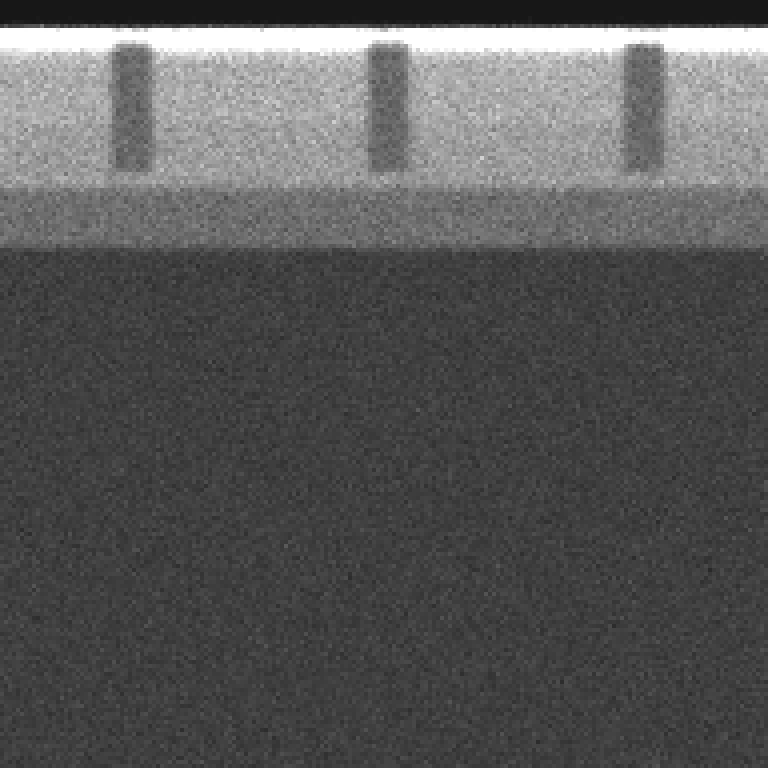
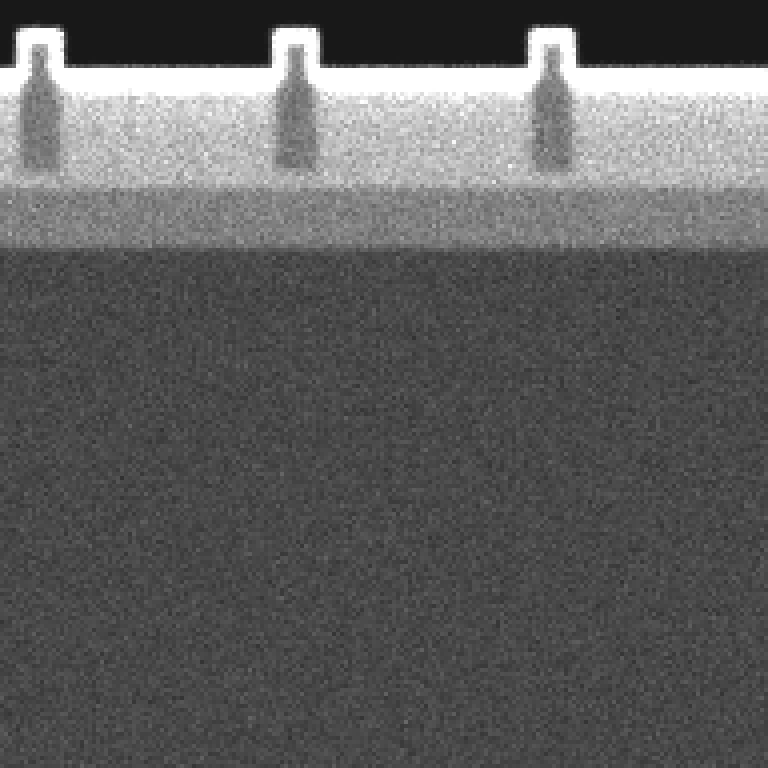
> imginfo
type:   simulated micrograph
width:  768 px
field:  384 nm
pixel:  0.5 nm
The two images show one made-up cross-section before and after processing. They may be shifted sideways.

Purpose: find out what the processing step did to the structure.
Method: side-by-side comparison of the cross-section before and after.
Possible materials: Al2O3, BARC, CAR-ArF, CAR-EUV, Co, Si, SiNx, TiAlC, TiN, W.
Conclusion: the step removed Al2O3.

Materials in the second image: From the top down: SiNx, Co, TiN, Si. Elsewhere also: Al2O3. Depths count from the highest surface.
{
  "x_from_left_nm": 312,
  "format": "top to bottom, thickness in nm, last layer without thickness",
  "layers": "empty 20, Al2O3 26, Co 32, TiN 30, Si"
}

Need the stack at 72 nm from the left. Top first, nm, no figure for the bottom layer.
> empty 20, Al2O3 26, Co 32, TiN 30, Si